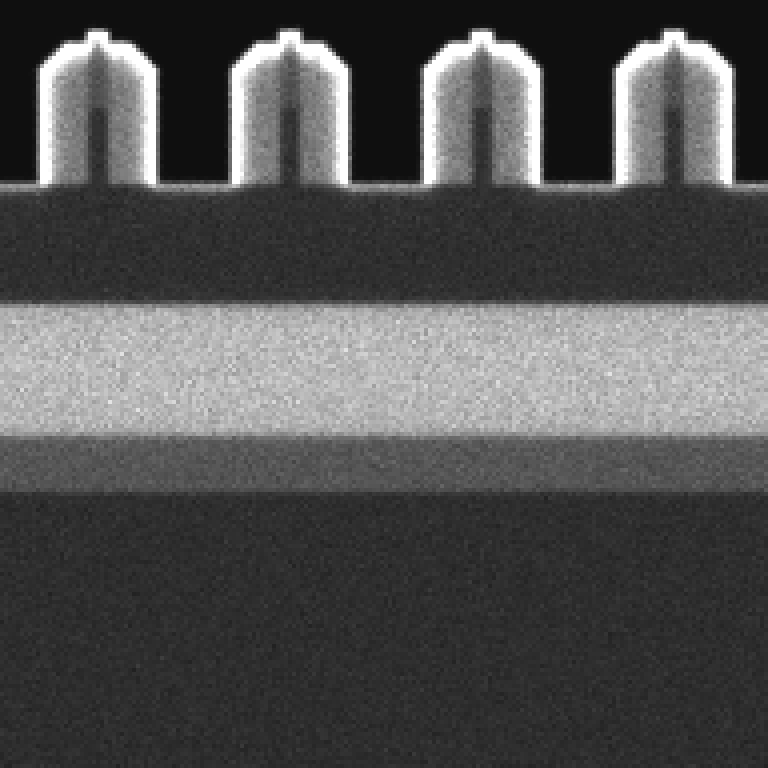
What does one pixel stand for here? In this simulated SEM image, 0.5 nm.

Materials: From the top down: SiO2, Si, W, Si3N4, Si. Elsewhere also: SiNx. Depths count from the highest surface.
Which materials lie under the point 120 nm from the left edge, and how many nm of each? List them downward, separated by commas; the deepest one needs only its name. empty 14, SiO2 62, Si 60, W 66, Si3N4 28, Si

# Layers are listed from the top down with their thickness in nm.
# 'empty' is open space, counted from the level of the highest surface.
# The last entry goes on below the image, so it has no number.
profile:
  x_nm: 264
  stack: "empty 14, SiO2 62, Si 60, W 66, Si3N4 28, Si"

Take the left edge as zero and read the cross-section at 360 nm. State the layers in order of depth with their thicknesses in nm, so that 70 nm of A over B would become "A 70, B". empty 14, SiO2 62, Si 60, W 66, Si3N4 28, Si